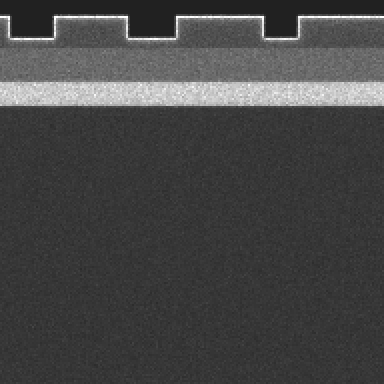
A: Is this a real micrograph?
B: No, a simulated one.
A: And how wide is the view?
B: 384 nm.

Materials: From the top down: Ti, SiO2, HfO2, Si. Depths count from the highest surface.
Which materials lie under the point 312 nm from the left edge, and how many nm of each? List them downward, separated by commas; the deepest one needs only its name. Ti 32, SiO2 34, HfO2 24, Si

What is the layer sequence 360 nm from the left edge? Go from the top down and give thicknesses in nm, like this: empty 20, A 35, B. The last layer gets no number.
Ti 32, SiO2 34, HfO2 24, Si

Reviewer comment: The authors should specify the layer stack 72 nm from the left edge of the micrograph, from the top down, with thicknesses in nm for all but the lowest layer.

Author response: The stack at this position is Ti 32, SiO2 34, HfO2 24, Si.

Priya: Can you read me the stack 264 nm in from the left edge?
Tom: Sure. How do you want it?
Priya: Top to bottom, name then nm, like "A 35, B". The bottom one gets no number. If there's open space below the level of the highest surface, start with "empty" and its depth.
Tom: empty 22, Ti 10, SiO2 34, HfO2 24, Si